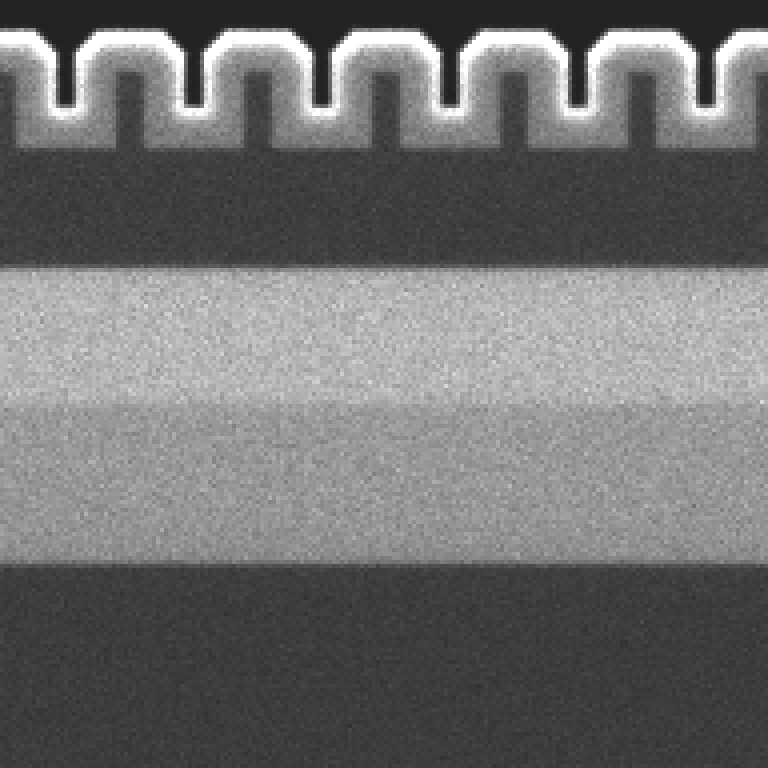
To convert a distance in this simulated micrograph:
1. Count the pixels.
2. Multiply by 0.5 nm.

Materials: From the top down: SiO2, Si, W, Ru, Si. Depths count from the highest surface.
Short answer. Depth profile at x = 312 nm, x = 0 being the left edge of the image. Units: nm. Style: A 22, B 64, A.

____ SiO2 58, Si 60, W 68, Ru 80, Si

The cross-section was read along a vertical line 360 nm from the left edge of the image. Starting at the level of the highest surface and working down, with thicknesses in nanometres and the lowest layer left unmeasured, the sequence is empty 8, SiO2 50, Si 60, W 68, Ru 80, Si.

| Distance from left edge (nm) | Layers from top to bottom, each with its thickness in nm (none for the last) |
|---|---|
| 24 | empty 8, SiO2 50, Si 60, W 68, Ru 80, Si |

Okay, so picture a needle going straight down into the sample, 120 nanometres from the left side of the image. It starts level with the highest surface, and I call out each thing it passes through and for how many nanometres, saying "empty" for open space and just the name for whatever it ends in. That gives SiO2 58, Si 60, W 68, Ru 80, Si